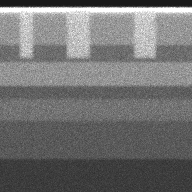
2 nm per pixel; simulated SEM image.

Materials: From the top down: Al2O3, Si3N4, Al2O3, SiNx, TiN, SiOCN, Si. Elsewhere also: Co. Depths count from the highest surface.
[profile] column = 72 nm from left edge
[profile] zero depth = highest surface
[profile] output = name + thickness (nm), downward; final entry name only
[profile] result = Al2O3 74, Si3N4 34, Al2O3 48, SiNx 26, TiN 44, SiOCN 76, Si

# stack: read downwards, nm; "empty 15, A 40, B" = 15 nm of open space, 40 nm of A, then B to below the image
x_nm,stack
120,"Al2O3 74, Si3N4 34, Al2O3 48, SiNx 26, TiN 44, SiOCN 76, Si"